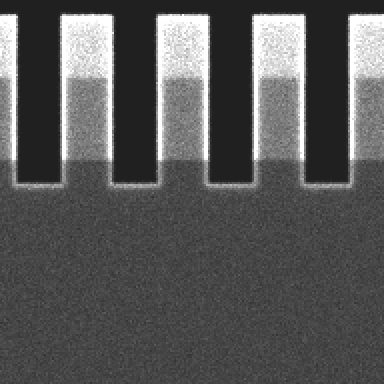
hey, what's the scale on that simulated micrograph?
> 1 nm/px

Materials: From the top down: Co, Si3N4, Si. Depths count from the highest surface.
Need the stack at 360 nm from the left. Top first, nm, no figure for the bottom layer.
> Co 62, Si3N4 82, Si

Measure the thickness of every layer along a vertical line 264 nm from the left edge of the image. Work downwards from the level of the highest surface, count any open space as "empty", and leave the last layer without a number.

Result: Co 62, Si3N4 82, Si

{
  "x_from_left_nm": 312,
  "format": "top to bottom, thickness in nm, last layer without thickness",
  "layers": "empty 168, Si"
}